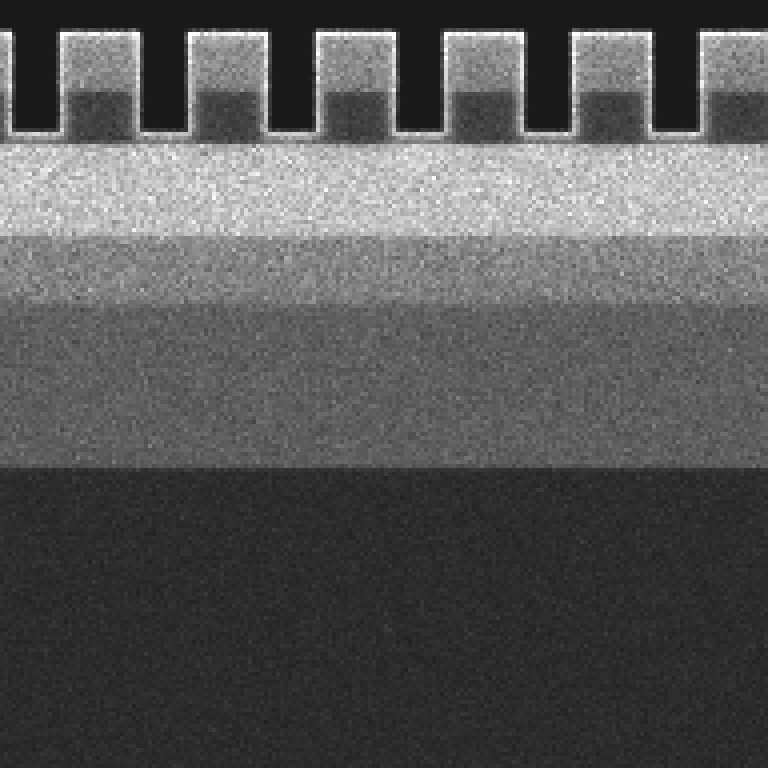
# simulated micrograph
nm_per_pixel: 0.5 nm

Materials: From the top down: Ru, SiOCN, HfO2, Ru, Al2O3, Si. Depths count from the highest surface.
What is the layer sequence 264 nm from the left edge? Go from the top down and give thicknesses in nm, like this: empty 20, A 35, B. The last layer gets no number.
empty 50, SiOCN 6, HfO2 46, Ru 34, Al2O3 82, Si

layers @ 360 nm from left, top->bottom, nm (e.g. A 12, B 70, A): Ru 30, SiOCN 26, HfO2 46, Ru 34, Al2O3 82, Si